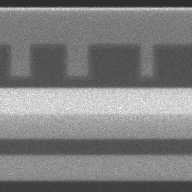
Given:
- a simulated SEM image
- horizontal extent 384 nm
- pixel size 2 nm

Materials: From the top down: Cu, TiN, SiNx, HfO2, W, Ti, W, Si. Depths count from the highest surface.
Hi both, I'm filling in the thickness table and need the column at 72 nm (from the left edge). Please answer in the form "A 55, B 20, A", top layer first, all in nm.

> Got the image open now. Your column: Cu 72, TiN 8, SiNx 80, HfO2 52, W 50, Ti 32, W 52, Si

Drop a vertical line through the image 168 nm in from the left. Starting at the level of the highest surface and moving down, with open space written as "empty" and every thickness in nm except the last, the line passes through Cu 136, TiN 8, SiNx 16, HfO2 52, W 50, Ti 32, W 52, Si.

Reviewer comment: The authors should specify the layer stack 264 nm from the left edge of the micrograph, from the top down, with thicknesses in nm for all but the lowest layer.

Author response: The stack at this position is Cu 72, TiN 8, SiNx 80, HfO2 52, W 50, Ti 32, W 52, Si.